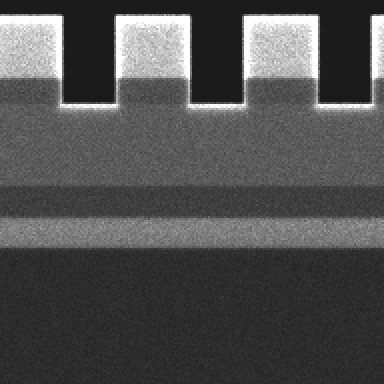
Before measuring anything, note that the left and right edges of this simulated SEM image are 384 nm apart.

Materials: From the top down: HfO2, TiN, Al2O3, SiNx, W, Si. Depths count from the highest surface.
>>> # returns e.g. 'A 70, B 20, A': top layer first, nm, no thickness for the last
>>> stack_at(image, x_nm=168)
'HfO2 62, TiN 26, Al2O3 82, SiNx 32, W 30, Si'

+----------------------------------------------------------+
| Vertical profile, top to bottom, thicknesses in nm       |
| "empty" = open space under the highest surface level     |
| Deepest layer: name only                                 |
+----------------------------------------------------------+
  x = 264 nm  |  HfO2 62, TiN 26, Al2O3 82, SiNx 32, W 30, Si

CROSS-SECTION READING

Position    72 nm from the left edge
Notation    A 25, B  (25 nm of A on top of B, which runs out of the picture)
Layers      empty 88, Al2O3 82, SiNx 32, W 30, Si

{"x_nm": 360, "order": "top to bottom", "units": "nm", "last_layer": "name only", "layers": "empty 88, Al2O3 82, SiNx 32, W 30, Si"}